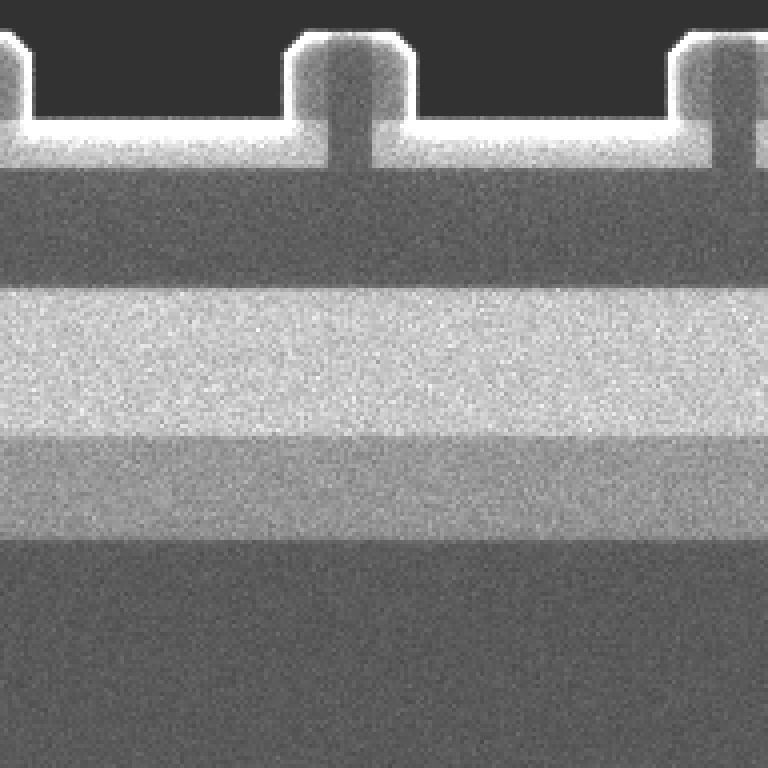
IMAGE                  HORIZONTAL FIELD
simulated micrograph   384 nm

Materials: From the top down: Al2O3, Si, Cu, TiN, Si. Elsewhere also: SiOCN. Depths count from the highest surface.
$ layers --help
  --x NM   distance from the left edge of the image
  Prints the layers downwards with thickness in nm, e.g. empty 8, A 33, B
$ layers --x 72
empty 44, Al2O3 24, Si 60, Cu 74, TiN 52, Si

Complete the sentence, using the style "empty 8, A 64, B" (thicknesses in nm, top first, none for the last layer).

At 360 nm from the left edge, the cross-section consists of Si 128, Cu 74, TiN 52, Si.